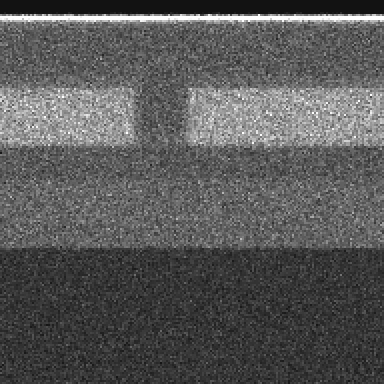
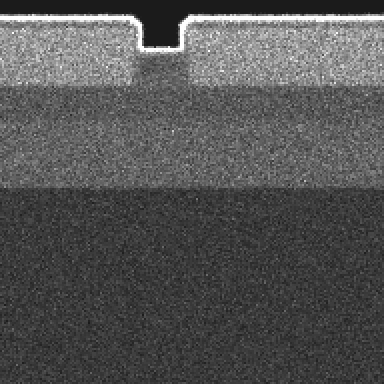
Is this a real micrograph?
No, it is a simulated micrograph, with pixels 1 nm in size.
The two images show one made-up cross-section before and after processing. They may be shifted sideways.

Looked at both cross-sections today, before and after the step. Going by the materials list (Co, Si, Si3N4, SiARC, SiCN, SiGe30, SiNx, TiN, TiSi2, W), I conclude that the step removed SiNx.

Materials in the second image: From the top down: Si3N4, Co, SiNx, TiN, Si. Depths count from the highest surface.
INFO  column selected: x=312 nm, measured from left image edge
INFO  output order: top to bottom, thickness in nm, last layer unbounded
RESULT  Si3N4 12, Co 58, SiNx 34, TiN 68, Si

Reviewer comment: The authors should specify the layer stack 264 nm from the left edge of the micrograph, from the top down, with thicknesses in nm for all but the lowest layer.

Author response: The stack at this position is Si3N4 12, Co 58, SiNx 34, TiN 68, Si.